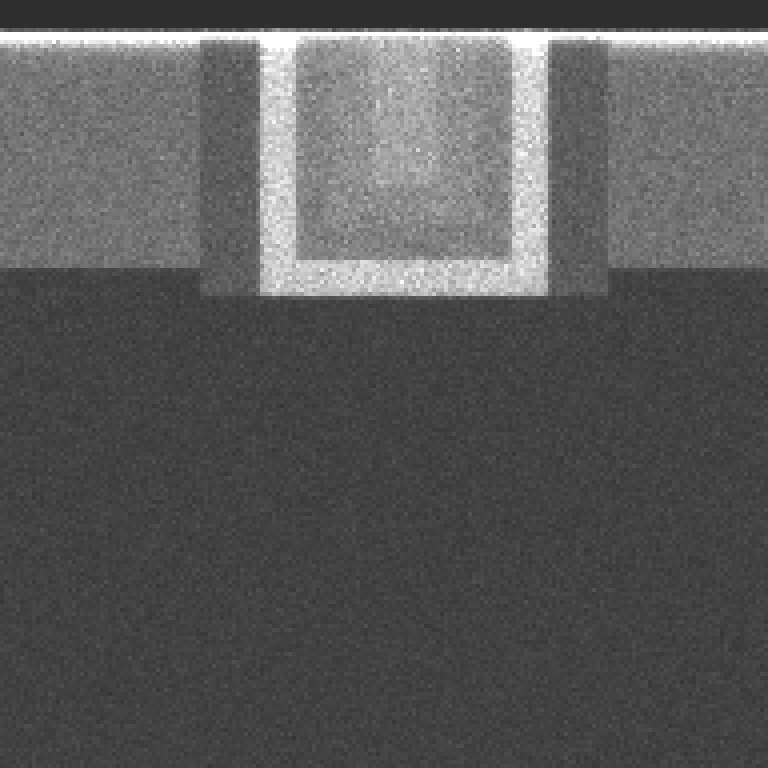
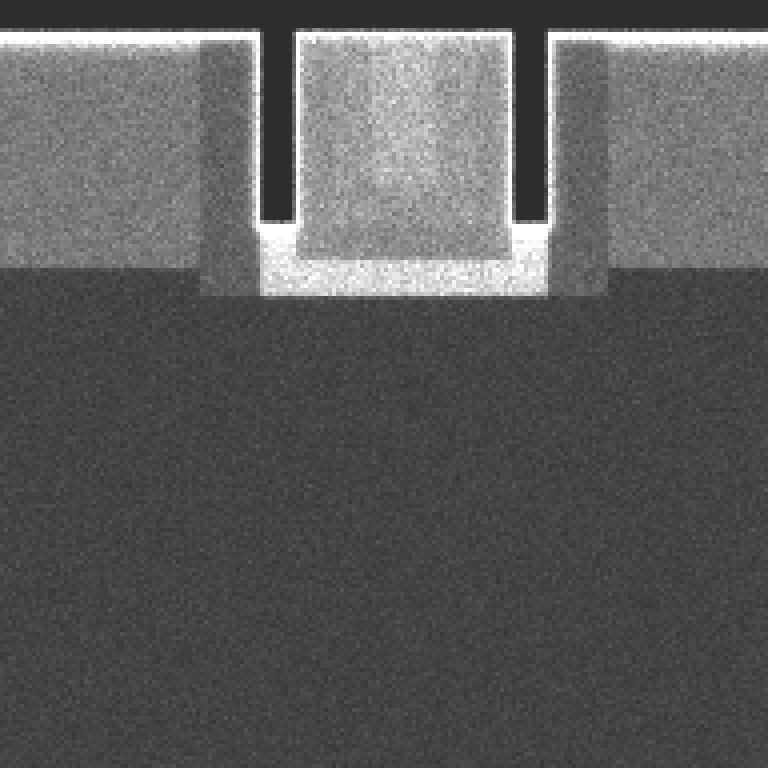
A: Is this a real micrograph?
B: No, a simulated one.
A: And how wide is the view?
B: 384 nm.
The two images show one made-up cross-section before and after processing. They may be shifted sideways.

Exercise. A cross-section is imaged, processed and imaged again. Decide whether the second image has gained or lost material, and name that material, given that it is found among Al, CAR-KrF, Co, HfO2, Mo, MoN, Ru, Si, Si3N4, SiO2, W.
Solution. removed: HfO2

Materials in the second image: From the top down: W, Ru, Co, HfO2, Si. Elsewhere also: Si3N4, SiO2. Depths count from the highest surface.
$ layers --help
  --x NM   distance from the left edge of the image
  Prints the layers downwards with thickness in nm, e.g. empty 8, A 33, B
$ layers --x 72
SiO2 118, Si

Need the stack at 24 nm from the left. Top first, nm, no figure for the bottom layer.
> SiO2 118, Si